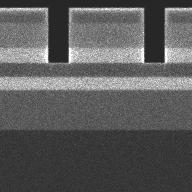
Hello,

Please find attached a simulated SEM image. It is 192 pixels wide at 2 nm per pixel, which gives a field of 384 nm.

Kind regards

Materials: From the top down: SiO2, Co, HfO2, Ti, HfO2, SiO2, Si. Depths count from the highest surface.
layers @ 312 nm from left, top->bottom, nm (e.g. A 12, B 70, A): empty 110, Ti 28, HfO2 26, SiO2 80, Si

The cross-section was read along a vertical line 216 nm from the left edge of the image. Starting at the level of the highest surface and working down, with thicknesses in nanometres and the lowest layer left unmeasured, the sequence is SiO2 30, Co 50, HfO2 30, Ti 28, HfO2 26, SiO2 80, Si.